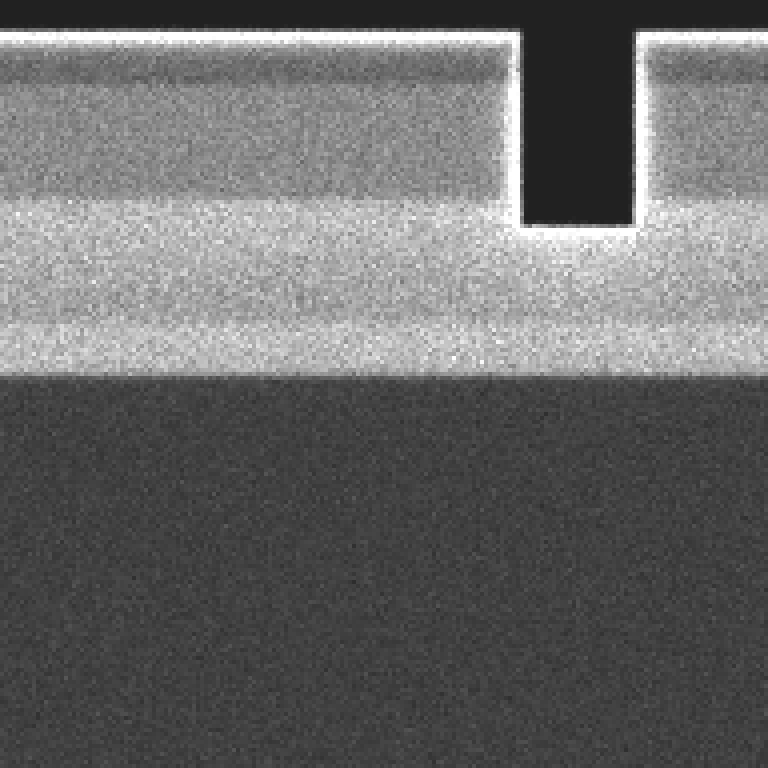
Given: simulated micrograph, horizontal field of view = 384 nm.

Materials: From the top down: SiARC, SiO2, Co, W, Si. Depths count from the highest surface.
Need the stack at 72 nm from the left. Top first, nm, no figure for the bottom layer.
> SiARC 26, SiO2 58, Co 62, W 26, Si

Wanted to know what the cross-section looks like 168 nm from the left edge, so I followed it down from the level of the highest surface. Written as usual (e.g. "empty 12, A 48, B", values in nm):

SiARC 26, SiO2 58, Co 62, W 26, Si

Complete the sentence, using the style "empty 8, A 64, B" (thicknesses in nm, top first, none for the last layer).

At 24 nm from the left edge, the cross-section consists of SiARC 26, SiO2 58, Co 62, W 26, Si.